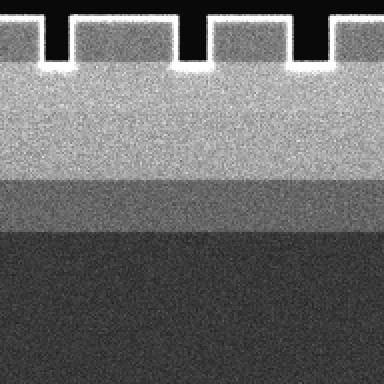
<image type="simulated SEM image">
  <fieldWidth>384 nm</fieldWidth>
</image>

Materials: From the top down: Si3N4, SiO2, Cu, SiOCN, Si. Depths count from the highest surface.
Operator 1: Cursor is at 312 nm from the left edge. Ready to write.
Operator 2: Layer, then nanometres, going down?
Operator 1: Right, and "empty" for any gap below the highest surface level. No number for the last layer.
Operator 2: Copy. empty 46, SiO2 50, Cu 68, SiOCN 52, Si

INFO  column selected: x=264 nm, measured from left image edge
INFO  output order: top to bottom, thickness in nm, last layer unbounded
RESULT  Si3N4 46, SiO2 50, Cu 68, SiOCN 52, Si